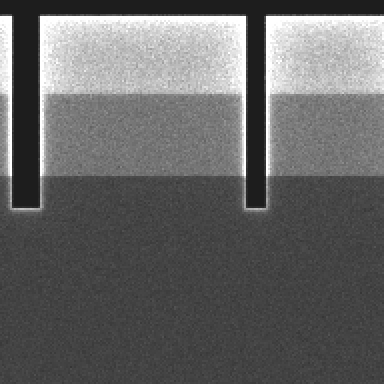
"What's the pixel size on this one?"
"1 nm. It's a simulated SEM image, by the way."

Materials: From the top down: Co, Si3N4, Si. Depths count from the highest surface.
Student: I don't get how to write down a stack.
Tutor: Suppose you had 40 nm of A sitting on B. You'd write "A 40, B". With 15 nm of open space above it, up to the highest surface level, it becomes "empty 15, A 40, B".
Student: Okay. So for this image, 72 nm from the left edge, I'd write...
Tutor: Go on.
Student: Co 78, Si3N4 82, Si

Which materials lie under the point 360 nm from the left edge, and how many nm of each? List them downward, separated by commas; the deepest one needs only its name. Co 78, Si3N4 82, Si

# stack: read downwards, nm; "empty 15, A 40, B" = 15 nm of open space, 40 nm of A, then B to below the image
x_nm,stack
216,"Co 78, Si3N4 82, Si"